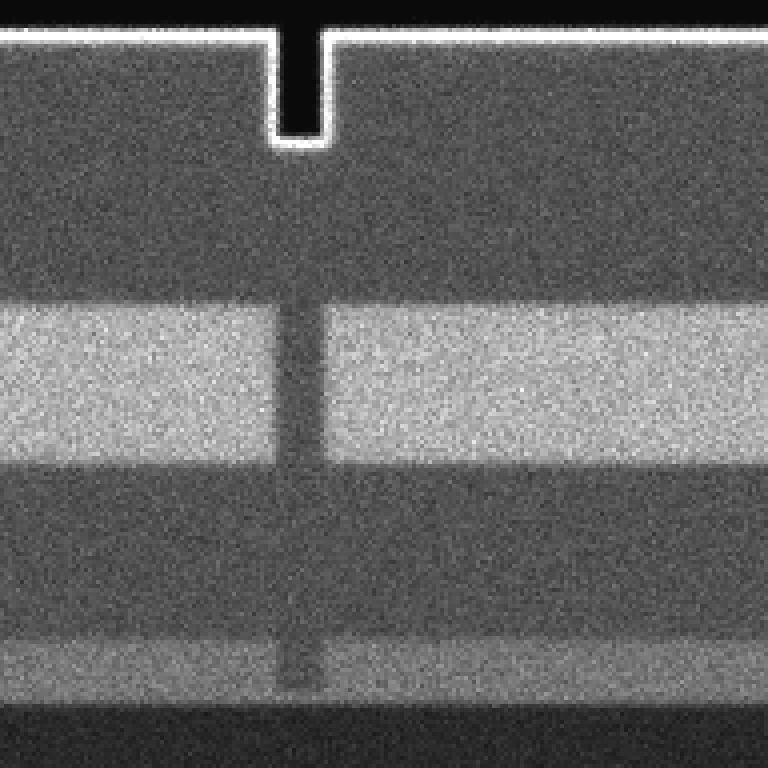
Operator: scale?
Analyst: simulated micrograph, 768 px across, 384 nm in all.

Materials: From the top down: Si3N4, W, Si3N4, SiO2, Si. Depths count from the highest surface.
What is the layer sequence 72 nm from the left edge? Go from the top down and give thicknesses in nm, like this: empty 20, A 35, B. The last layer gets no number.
Si3N4 136, W 80, Si3N4 88, SiO2 32, Si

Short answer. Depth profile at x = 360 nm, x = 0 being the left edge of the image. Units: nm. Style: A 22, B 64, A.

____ Si3N4 136, W 80, Si3N4 88, SiO2 32, Si